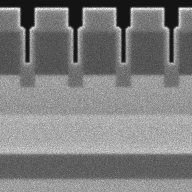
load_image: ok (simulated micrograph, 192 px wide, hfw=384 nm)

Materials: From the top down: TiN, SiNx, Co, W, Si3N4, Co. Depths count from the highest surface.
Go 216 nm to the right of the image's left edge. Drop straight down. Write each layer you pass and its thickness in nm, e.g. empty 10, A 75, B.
TiN 48, SiNx 86, Co 80, W 78, Si3N4 50, Co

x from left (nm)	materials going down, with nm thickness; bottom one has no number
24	TiN 48, SiNx 86, Co 80, W 78, Si3N4 50, Co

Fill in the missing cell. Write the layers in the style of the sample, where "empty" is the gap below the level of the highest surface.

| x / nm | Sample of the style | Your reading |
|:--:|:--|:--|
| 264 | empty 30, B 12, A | TiN 48, SiNx 86, Co 80, W 78, Si3N4 50, Co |